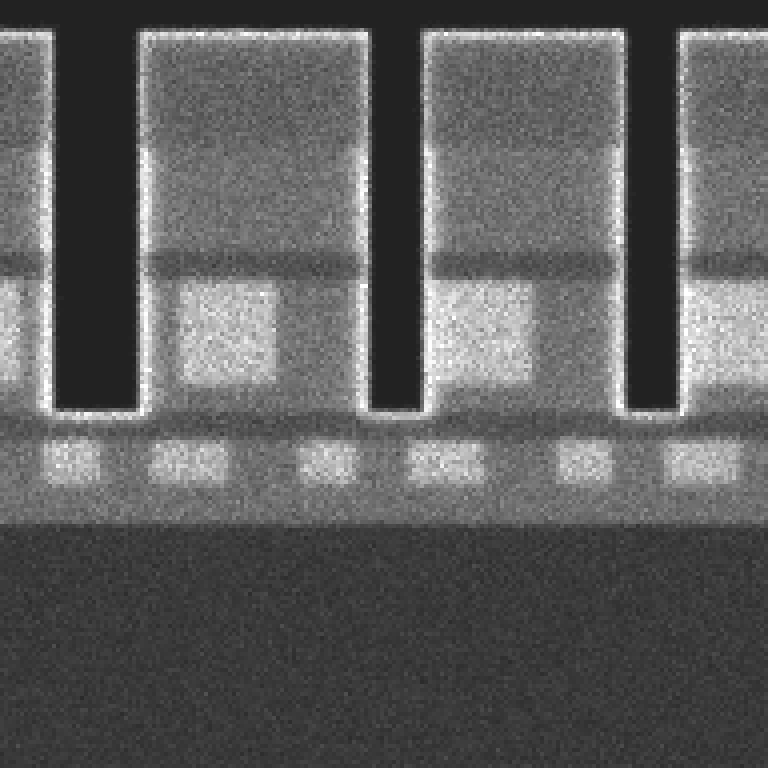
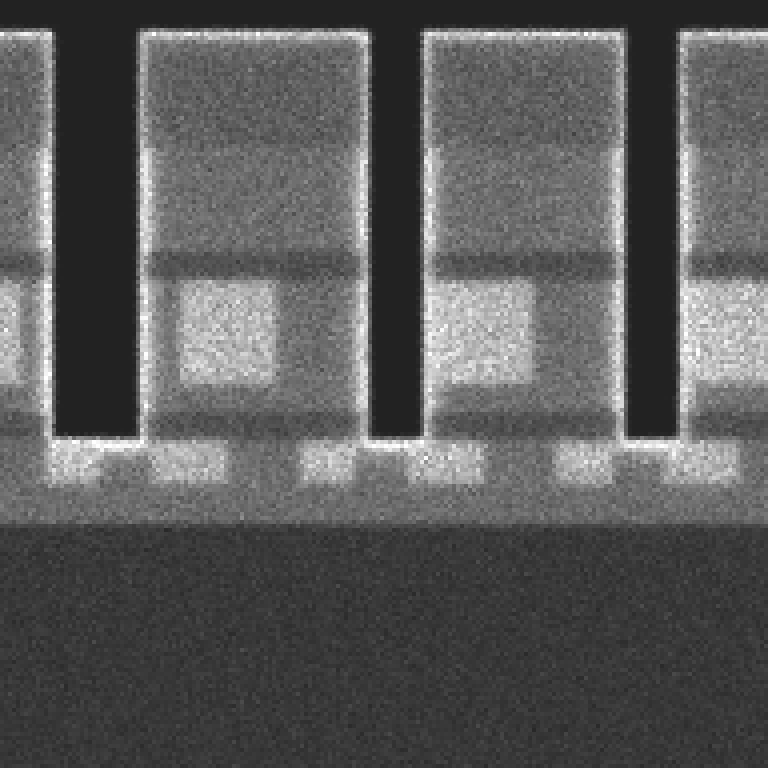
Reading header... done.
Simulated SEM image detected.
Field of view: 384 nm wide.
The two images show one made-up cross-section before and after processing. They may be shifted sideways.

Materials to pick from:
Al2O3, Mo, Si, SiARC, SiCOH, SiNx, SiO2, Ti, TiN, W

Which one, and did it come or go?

SiNx - removed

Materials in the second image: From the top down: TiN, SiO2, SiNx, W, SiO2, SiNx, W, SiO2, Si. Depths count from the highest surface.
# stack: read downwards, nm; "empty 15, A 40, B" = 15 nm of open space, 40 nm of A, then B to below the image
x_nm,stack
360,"TiN 58, SiO2 52, SiNx 14, W 52, SiO2 14, SiNx 14, W 22, SiO2 20, Si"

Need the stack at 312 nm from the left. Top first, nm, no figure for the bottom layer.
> empty 204, SiO2 42, Si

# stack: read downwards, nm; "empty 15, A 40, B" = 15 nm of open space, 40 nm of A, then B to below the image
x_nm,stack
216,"TiN 58, SiO2 52, SiNx 14, SiO2 66, SiNx 14, W 22, SiO2 20, Si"